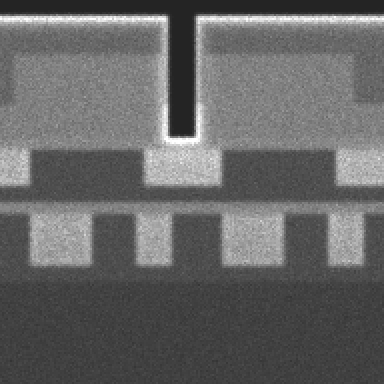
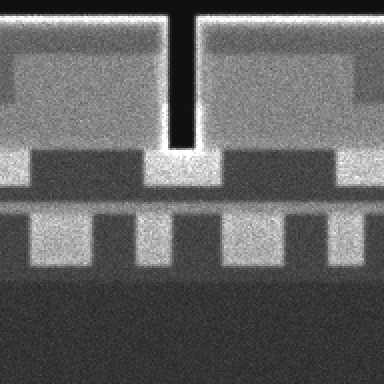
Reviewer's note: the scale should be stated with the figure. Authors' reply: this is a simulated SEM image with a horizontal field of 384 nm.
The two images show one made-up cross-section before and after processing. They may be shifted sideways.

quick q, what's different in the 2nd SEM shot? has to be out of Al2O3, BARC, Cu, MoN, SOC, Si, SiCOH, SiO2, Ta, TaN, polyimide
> Al2O3 removed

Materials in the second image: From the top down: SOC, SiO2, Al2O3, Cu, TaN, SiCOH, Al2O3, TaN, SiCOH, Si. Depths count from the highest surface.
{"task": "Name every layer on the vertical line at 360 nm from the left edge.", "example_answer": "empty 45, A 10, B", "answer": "SOC 88, SiO2 34, Al2O3 12, Cu 28, TaN 8, SiCOH 16, Al2O3 12, TaN 52, SiCOH 16, Si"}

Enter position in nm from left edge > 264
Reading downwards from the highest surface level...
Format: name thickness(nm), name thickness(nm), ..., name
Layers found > SOC 38, SiO2 84, Al2O3 12, SiCOH 52, Al2O3 12, Cu 44, TaN 8, SiCOH 16, Si